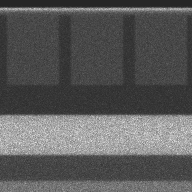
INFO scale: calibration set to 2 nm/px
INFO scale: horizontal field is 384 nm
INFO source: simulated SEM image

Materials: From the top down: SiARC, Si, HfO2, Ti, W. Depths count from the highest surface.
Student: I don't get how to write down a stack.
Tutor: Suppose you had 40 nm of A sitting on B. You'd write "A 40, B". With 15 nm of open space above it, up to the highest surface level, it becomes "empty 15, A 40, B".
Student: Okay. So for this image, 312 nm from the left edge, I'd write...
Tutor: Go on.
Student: SiARC 154, Si 60, HfO2 80, Ti 52, W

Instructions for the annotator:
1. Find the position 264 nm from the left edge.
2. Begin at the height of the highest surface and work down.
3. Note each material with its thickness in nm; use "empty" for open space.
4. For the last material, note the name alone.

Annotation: SiARC 14, Si 200, HfO2 80, Ti 52, W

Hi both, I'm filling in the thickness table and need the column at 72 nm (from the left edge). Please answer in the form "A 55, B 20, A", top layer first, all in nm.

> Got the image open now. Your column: SiARC 154, Si 60, HfO2 80, Ti 52, W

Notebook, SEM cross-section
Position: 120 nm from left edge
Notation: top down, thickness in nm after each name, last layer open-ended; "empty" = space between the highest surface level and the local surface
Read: SiARC 14, Si 200, HfO2 80, Ti 52, W